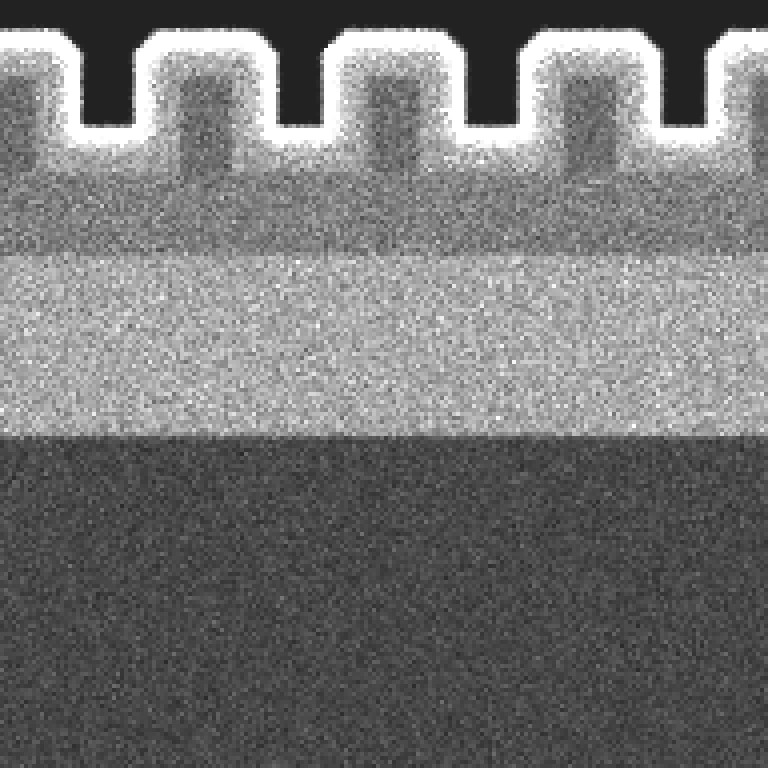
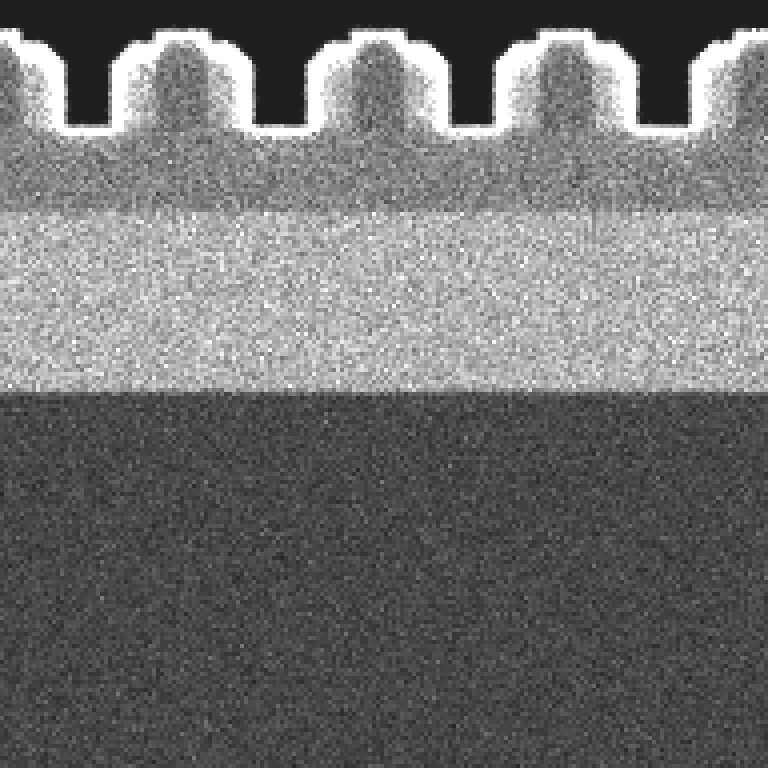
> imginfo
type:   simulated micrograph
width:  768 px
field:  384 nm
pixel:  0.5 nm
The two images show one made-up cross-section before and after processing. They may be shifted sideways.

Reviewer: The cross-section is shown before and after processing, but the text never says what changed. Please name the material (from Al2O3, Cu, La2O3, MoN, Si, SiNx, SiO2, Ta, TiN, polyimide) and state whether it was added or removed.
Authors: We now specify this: SiO2, removed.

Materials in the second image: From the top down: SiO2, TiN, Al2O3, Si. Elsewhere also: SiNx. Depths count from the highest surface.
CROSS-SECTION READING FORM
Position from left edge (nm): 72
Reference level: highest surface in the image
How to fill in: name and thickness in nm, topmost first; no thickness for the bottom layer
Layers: empty 6, SiO2 42, TiN 42, Al2O3 90, Si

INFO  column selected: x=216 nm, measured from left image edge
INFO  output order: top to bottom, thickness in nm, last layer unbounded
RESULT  empty 10, SiO2 38, TiN 42, Al2O3 90, Si